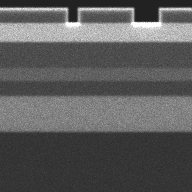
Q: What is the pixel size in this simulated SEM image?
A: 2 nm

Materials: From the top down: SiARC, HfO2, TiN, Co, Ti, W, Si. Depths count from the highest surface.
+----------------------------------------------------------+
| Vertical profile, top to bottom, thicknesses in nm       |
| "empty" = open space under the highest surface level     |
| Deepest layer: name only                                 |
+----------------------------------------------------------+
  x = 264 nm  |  SiARC 30, HfO2 38, TiN 52, Co 26, Ti 30, W 72, Si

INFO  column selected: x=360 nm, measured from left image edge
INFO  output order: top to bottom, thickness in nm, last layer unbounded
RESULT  SiARC 30, HfO2 38, TiN 52, Co 26, Ti 30, W 72, Si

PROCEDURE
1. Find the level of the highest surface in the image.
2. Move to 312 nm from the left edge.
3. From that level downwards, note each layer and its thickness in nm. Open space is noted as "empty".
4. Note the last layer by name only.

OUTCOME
empty 30, HfO2 38, TiN 52, Co 26, Ti 30, W 72, Si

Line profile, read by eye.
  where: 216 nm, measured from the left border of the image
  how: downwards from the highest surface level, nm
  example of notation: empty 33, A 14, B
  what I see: SiARC 30, HfO2 38, TiN 52, Co 26, Ti 30, W 72, Si